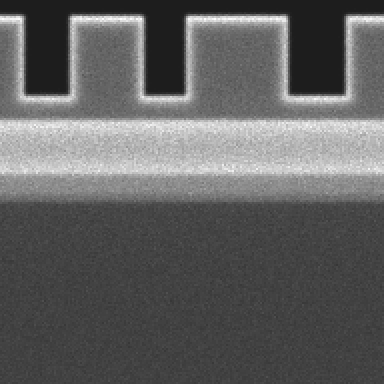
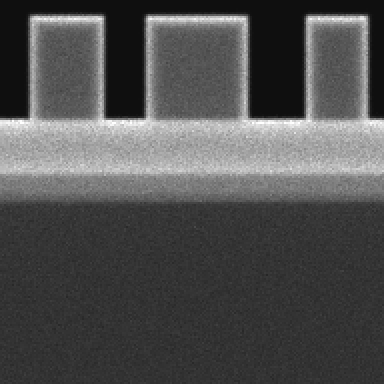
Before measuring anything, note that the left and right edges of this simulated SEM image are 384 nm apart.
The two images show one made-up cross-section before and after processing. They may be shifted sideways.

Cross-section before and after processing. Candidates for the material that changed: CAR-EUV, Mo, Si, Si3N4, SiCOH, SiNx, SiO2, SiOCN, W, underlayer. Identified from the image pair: underlayer (removed).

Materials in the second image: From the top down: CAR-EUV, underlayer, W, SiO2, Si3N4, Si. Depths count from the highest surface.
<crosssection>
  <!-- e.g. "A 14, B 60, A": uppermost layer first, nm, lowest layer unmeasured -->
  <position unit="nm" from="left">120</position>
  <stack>empty 104, W 54, SiO2 20, Si3N4 8, Si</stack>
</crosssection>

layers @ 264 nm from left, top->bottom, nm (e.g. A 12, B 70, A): empty 104, W 54, SiO2 20, Si3N4 8, Si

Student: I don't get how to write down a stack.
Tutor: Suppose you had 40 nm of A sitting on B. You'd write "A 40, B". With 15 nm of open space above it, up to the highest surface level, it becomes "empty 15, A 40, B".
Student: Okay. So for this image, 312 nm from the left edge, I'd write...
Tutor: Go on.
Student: CAR-EUV 80, underlayer 24, W 54, SiO2 20, Si3N4 8, Si